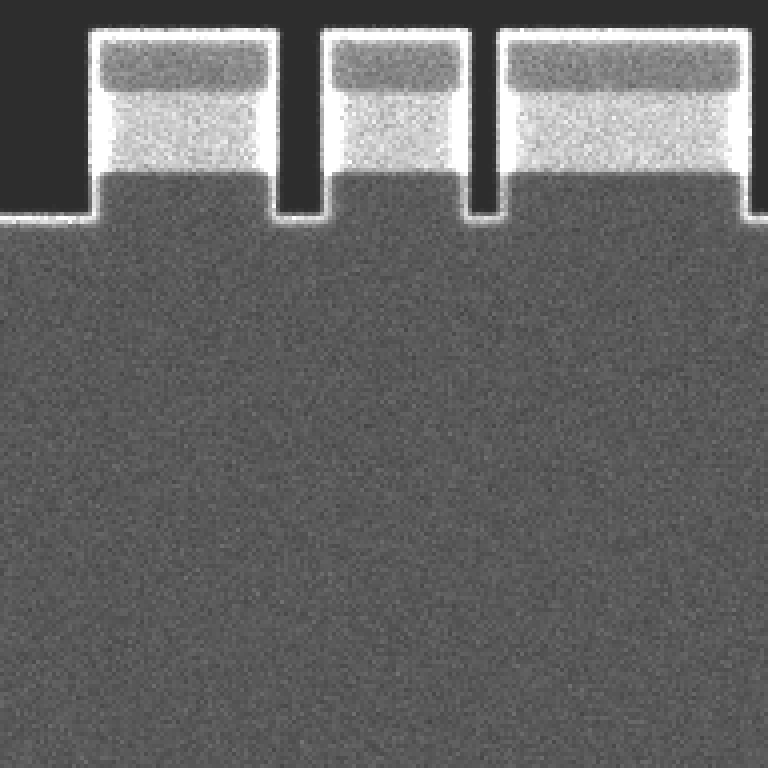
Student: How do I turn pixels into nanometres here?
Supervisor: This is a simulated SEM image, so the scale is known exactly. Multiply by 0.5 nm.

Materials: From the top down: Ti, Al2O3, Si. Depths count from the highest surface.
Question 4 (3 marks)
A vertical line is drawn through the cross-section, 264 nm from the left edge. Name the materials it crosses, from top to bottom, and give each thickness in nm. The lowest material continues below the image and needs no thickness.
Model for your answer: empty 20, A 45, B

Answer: Ti 30, Al2O3 40, Si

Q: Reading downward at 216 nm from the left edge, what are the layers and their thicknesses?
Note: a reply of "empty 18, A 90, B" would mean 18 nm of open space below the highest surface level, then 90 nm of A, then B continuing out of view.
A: Ti 30, Al2O3 40, Si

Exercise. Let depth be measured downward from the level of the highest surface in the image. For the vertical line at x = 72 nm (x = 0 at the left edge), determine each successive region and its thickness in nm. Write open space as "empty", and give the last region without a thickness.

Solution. Ti 30, Al2O3 40, Si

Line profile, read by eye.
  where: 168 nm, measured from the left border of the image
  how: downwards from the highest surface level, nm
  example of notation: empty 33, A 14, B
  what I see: Ti 30, Al2O3 40, Si